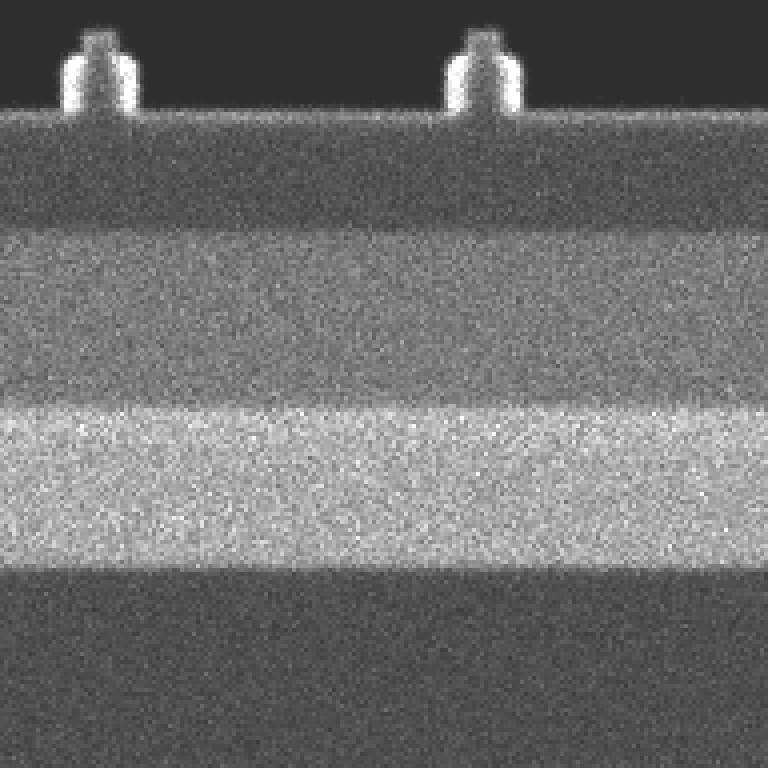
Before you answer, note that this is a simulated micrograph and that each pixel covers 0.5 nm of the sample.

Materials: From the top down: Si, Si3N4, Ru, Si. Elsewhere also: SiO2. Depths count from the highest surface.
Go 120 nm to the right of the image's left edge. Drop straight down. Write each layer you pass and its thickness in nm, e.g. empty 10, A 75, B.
empty 40, Si 60, Si3N4 88, Ru 80, Si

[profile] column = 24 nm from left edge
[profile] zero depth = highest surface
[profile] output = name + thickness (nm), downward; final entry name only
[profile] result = empty 40, Si 60, Si3N4 88, Ru 80, Si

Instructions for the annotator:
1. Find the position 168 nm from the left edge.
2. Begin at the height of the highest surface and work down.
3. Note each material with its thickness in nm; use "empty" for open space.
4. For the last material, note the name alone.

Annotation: empty 40, Si 60, Si3N4 88, Ru 80, Si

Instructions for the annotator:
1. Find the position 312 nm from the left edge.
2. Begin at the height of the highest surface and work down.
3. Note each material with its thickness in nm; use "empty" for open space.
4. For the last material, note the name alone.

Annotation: empty 40, Si 60, Si3N4 88, Ru 80, Si